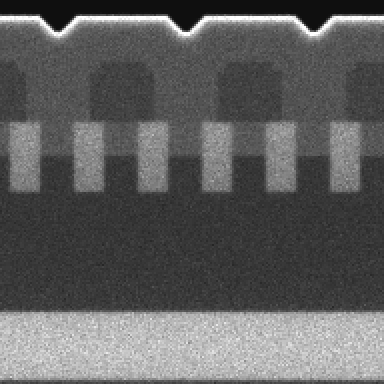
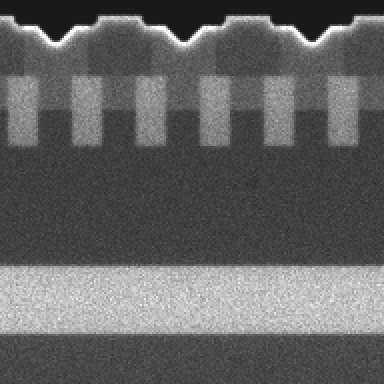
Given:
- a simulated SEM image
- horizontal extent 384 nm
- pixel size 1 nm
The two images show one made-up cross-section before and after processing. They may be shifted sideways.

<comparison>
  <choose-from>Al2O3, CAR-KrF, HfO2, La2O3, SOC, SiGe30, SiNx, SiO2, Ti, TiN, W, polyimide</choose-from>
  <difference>SiO2 removed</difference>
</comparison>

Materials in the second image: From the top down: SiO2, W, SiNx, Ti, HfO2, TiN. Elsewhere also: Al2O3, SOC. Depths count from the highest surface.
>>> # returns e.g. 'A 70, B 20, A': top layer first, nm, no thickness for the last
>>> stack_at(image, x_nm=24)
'empty 10, SiO2 50, W 70, SiNx 36, Ti 84, HfO2 68, TiN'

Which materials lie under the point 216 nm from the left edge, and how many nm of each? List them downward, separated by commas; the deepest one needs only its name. empty 10, SOC 50, W 70, SiNx 36, Ti 84, HfO2 68, TiN